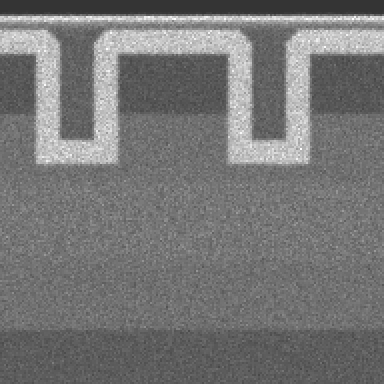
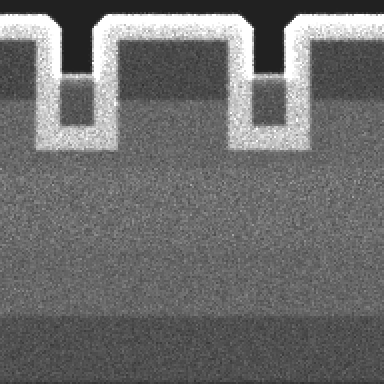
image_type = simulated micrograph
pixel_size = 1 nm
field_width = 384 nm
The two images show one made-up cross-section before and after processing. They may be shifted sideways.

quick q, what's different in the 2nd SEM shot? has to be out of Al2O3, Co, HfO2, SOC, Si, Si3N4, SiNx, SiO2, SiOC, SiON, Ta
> SOC removed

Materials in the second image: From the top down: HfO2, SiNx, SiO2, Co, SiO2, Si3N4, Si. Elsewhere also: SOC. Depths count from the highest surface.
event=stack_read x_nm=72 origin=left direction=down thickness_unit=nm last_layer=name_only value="empty 58, SOC 52, HfO2 24, SiO2 18, Co 80, SiO2 68, Si3N4 66, Si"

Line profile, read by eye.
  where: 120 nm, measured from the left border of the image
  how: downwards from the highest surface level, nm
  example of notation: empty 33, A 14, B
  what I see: HfO2 24, SiNx 60, SiO2 68, Co 80, SiO2 68, Si3N4 66, Si